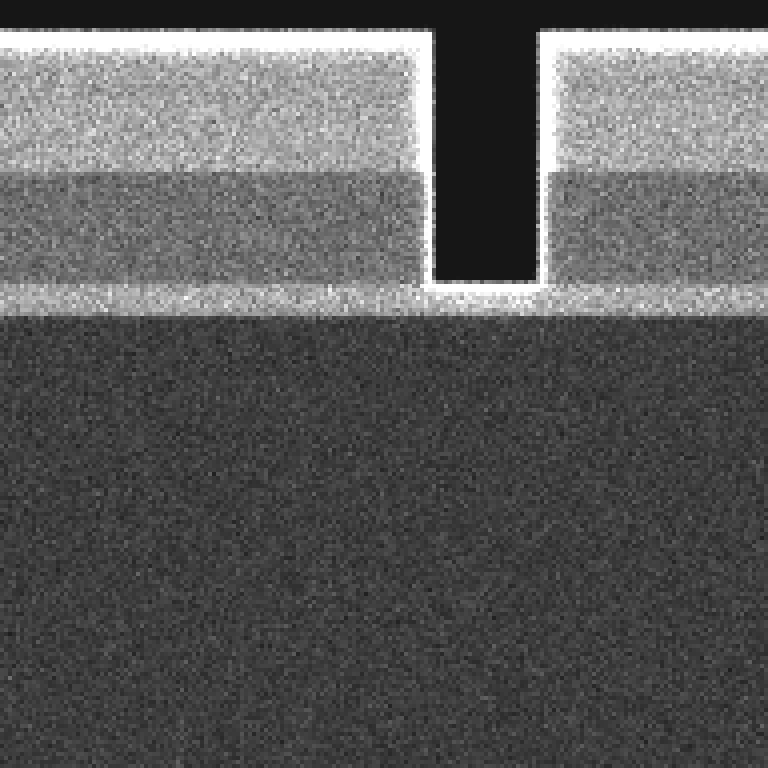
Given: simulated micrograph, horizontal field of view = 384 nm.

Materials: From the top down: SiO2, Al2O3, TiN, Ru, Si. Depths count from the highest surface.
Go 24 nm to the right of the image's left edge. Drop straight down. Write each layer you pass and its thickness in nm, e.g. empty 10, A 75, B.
SiO2 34, Al2O3 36, TiN 56, Ru 16, Si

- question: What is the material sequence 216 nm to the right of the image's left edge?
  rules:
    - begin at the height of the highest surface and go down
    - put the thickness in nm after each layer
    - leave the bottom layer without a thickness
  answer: empty 126, Ru 16, Si